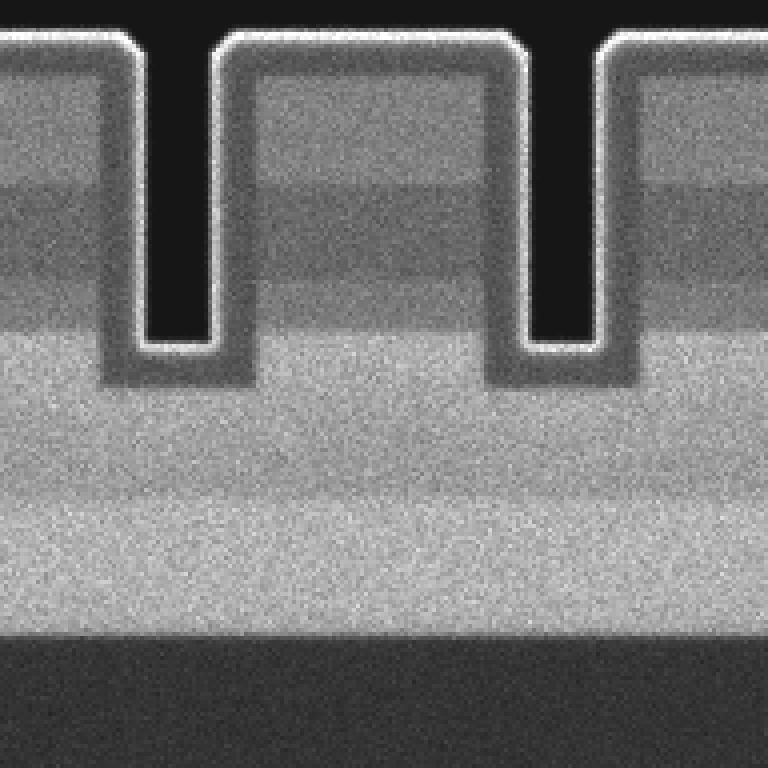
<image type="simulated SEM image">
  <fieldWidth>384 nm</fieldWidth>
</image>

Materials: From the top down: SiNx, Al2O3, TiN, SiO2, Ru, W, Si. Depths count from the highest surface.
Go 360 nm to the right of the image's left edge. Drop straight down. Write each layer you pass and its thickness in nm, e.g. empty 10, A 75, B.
SiNx 22, Al2O3 54, TiN 48, SiO2 26, Ru 84, W 68, Si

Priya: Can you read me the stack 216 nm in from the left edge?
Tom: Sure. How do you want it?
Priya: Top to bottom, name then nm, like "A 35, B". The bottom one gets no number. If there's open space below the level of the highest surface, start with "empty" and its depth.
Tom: SiNx 22, Al2O3 54, TiN 48, SiO2 26, Ru 84, W 68, Si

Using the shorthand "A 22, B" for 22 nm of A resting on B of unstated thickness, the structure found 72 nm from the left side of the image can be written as empty 156, SiNx 22, Ru 56, W 68, Si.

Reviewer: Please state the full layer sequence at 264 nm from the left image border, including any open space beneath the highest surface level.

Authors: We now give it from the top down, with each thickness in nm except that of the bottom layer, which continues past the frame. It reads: empty 156, SiNx 22, Ru 56, W 68, Si